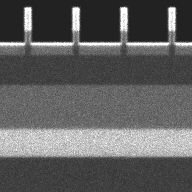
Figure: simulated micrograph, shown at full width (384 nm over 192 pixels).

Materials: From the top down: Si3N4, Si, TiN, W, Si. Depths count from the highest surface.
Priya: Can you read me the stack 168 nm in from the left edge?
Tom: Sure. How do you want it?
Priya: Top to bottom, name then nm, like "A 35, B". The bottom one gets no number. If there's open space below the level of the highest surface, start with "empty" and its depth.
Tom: empty 70, Si3N4 24, Si 60, TiN 88, W 56, Si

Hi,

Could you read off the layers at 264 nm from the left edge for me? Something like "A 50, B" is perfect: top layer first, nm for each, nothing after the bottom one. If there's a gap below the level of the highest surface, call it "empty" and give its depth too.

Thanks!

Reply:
empty 70, Si3N4 24, Si 60, TiN 88, W 56, Si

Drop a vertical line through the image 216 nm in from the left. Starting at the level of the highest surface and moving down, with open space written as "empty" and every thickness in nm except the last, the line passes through empty 70, Si3N4 24, Si 60, TiN 88, W 56, Si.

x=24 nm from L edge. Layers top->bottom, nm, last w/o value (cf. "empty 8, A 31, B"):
empty 70, Si3N4 24, Si 60, TiN 88, W 56, Si